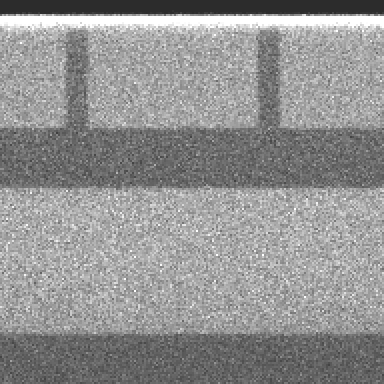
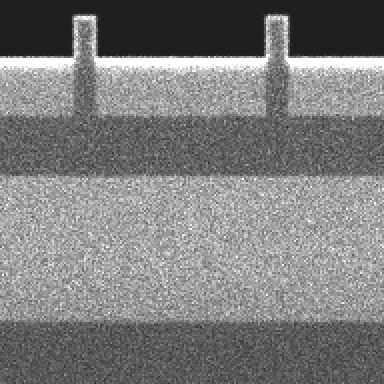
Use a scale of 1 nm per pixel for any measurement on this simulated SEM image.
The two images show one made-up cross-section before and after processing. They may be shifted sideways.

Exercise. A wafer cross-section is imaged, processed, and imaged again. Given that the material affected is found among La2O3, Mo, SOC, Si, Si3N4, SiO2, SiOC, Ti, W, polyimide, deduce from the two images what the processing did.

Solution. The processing removed SOC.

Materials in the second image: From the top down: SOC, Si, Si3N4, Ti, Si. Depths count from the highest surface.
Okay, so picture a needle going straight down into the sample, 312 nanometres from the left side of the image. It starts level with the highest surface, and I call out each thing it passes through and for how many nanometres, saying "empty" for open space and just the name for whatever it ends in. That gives empty 42, SOC 58, Si 60, Si3N4 78, Ti 68, Si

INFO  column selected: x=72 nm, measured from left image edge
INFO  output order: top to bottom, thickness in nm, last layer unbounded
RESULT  empty 42, SOC 58, Si 60, Si3N4 78, Ti 68, Si